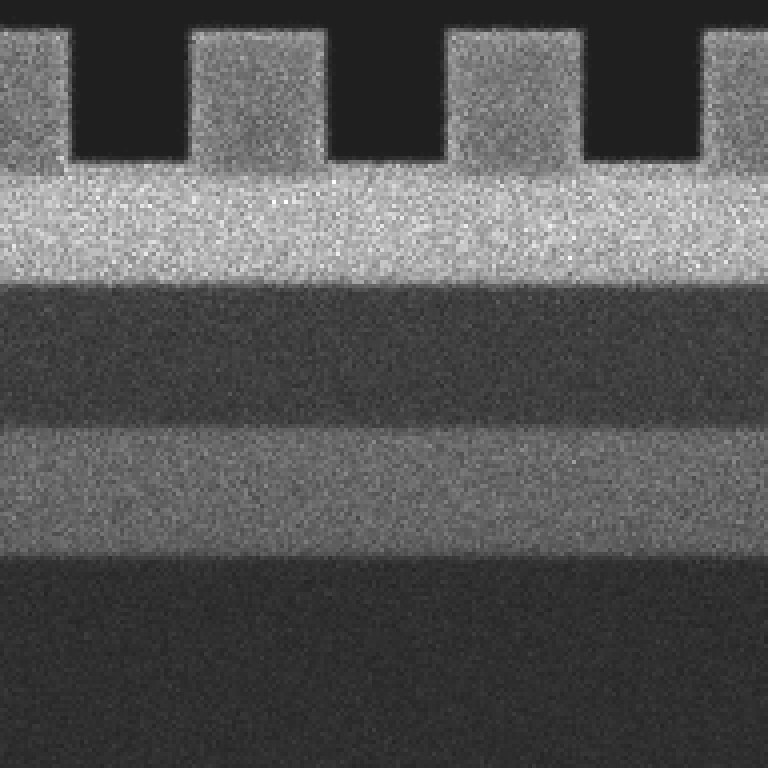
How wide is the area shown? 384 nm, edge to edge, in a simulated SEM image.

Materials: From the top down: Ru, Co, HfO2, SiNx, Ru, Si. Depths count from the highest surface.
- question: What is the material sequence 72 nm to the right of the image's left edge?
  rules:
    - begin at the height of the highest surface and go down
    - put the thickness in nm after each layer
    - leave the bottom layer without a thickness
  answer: empty 66, Co 6, HfO2 54, SiNx 72, Ru 64, Si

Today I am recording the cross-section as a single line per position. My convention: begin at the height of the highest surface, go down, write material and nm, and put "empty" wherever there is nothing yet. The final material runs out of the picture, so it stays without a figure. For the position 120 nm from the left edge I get Ru 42, Co 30, HfO2 54, SiNx 72, Ru 64, Si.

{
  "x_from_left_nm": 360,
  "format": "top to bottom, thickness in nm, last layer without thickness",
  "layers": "Ru 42, Co 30, HfO2 54, SiNx 72, Ru 64, Si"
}